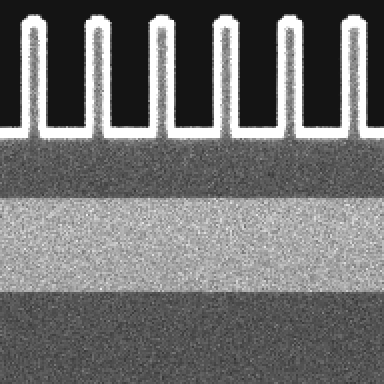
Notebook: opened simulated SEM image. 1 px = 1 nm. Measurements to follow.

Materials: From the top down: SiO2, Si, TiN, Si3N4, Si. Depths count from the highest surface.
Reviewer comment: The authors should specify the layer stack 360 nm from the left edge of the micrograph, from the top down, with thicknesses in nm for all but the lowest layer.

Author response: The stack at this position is empty 4, SiO2 118, Si 60, TiN 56, Si3N4 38, Si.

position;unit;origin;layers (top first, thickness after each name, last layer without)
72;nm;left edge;empty 112, SiO2 10, Si 60, TiN 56, Si3N4 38, Si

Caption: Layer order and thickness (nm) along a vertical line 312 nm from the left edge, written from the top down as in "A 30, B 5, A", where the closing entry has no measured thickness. empty 112, SiO2 10, Si 60, TiN 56, Si3N4 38, Si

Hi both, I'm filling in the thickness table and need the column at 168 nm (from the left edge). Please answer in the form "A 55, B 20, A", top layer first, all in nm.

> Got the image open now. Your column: empty 4, SiO2 118, Si 60, TiN 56, Si3N4 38, Si